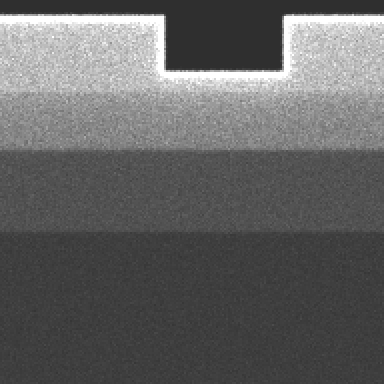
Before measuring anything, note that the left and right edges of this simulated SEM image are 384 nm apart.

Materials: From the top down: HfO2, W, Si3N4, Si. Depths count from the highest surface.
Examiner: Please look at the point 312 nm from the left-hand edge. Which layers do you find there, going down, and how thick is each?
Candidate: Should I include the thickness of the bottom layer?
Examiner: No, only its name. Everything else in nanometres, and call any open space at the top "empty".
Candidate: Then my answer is HfO2 76, W 58, Si3N4 82, Si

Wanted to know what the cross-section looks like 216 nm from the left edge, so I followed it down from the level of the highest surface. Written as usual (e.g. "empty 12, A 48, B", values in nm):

empty 56, HfO2 20, W 58, Si3N4 82, Si